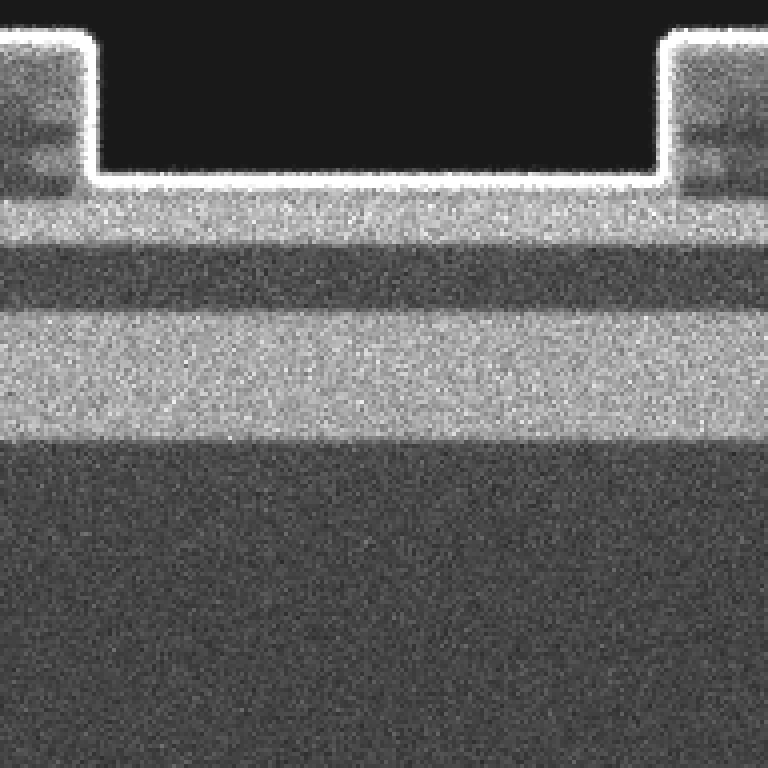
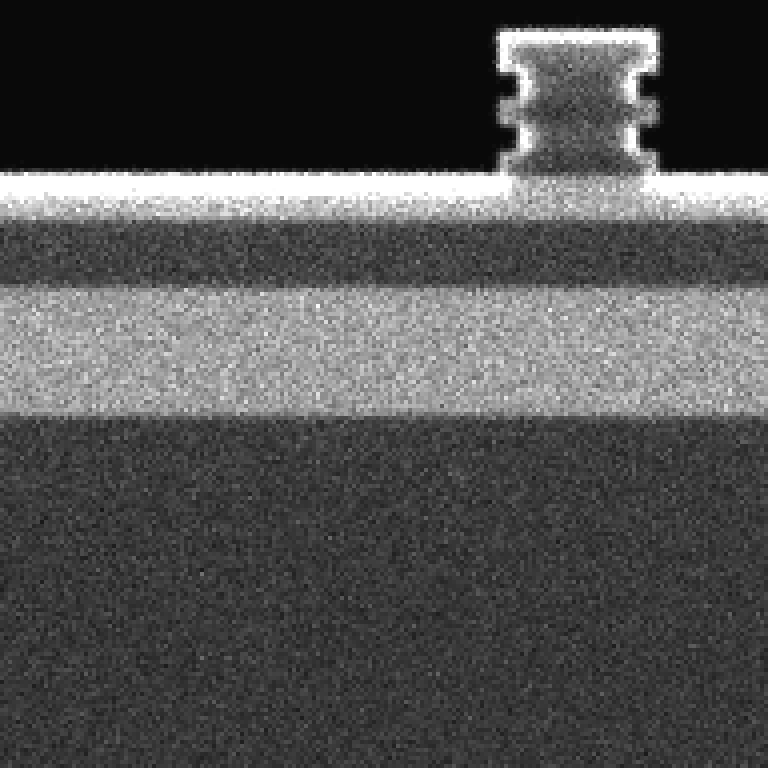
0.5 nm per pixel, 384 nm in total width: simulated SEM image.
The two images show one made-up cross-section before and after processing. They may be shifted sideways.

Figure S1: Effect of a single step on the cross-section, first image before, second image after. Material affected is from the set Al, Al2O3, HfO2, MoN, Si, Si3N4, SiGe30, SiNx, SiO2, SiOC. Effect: removed Si3N4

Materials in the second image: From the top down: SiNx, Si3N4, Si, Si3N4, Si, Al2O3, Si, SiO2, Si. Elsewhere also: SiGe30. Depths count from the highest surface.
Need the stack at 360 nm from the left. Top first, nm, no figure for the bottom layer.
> empty 72, Al2O3 22, Si 34, SiO2 64, Si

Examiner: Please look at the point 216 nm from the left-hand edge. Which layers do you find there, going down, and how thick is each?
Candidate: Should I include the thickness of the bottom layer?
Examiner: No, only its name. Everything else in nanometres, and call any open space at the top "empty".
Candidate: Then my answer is empty 72, Al2O3 22, Si 34, SiO2 64, Si